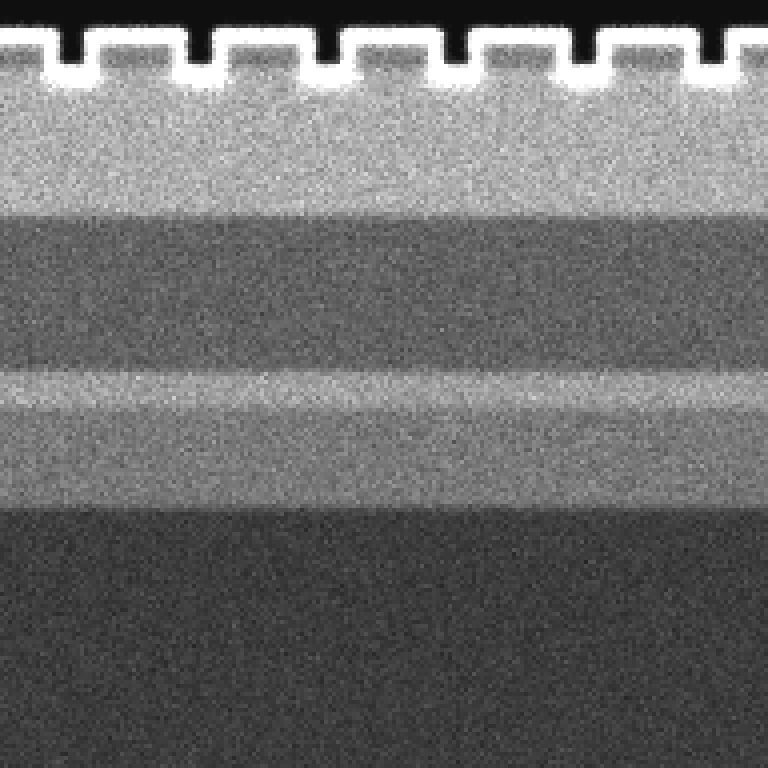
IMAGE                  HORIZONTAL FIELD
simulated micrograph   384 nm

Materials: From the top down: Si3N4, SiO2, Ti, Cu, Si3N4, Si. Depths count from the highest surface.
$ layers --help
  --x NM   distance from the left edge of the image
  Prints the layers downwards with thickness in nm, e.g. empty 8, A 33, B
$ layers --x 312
Si3N4 18, SiO2 74, Ti 78, Cu 18, Si3N4 50, Si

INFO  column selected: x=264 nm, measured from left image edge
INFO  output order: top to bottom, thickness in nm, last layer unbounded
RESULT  Si3N4 18, SiO2 74, Ti 78, Cu 18, Si3N4 50, Si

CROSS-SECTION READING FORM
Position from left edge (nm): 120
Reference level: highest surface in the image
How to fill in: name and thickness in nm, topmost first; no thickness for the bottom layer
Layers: Si3N4 18, SiO2 74, Ti 78, Cu 18, Si3N4 50, Si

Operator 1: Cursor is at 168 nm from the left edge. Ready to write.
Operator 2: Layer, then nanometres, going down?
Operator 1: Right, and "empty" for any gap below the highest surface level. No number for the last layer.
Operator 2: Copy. empty 18, SiO2 74, Ti 78, Cu 18, Si3N4 50, Si